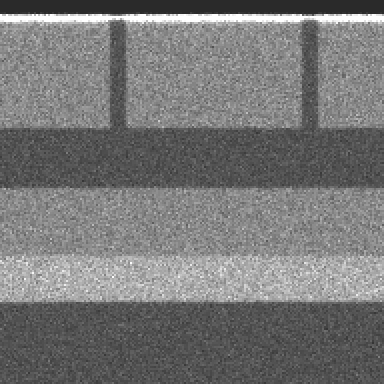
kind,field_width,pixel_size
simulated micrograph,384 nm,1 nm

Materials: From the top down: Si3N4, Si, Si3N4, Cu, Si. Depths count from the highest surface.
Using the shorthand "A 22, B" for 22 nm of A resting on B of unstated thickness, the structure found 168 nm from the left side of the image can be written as Si3N4 112, Si 60, Si3N4 68, Cu 46, Si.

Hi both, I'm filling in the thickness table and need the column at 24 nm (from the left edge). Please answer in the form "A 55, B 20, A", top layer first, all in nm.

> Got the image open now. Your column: Si3N4 112, Si 60, Si3N4 68, Cu 46, Si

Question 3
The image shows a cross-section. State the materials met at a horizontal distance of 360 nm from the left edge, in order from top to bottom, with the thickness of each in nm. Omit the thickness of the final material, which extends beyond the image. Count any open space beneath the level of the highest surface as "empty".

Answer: Si3N4 112, Si 60, Si3N4 68, Cu 46, Si